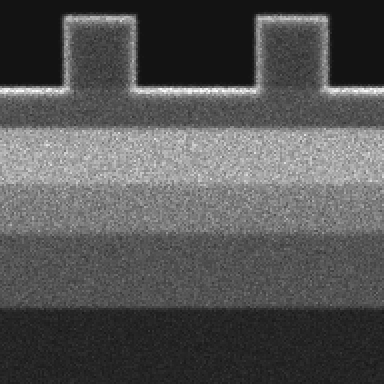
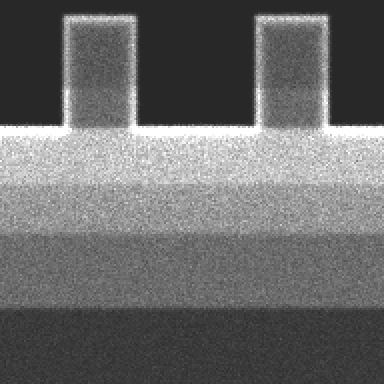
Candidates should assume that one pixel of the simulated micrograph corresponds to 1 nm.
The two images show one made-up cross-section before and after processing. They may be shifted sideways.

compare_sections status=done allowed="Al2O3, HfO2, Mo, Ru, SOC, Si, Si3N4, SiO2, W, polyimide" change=removed material="SiO2"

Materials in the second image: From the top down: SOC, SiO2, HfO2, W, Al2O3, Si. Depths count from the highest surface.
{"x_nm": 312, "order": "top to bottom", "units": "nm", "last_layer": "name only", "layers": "SOC 72, SiO2 40, HfO2 56, W 50, Al2O3 74, Si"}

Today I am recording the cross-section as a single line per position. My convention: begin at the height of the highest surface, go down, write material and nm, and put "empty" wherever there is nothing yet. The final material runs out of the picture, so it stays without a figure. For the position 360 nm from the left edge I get empty 112, HfO2 56, W 50, Al2O3 74, Si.